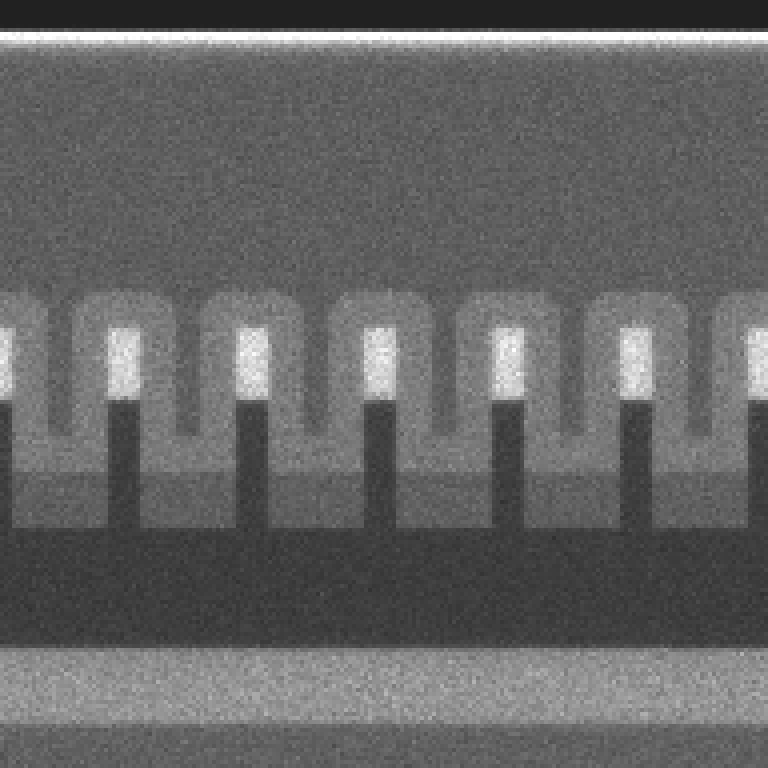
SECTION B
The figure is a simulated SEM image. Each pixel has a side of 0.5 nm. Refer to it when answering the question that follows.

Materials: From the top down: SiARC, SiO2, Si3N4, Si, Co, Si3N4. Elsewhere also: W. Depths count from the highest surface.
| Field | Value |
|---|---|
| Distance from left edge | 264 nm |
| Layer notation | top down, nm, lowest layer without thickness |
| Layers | SiARC 130, SiO2 90, Si3N4 28, Si 60, Co 38, Si3N4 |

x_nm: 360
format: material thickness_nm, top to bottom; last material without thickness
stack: SiARC 134, SiO2 86, Si3N4 28, Si 60, Co 38, Si3N4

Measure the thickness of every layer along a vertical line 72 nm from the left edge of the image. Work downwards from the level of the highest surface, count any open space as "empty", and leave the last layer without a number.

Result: SiARC 130, SiO2 90, Si3N4 28, Si 60, Co 38, Si3N4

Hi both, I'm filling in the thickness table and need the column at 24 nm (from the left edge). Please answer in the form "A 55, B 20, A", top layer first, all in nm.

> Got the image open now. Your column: SiARC 202, SiO2 18, Si3N4 28, Si 60, Co 38, Si3N4